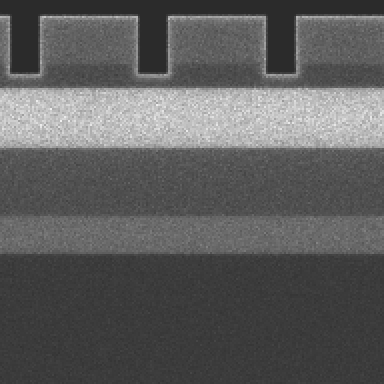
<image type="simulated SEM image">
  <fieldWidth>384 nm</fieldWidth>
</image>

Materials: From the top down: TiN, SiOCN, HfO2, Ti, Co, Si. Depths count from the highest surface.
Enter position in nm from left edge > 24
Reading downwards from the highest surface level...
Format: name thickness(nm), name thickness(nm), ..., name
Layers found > empty 58, SiOCN 14, HfO2 60, Ti 68, Co 38, Si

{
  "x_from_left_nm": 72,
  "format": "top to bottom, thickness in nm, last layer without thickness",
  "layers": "TiN 48, SiOCN 24, HfO2 60, Ti 68, Co 38, Si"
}